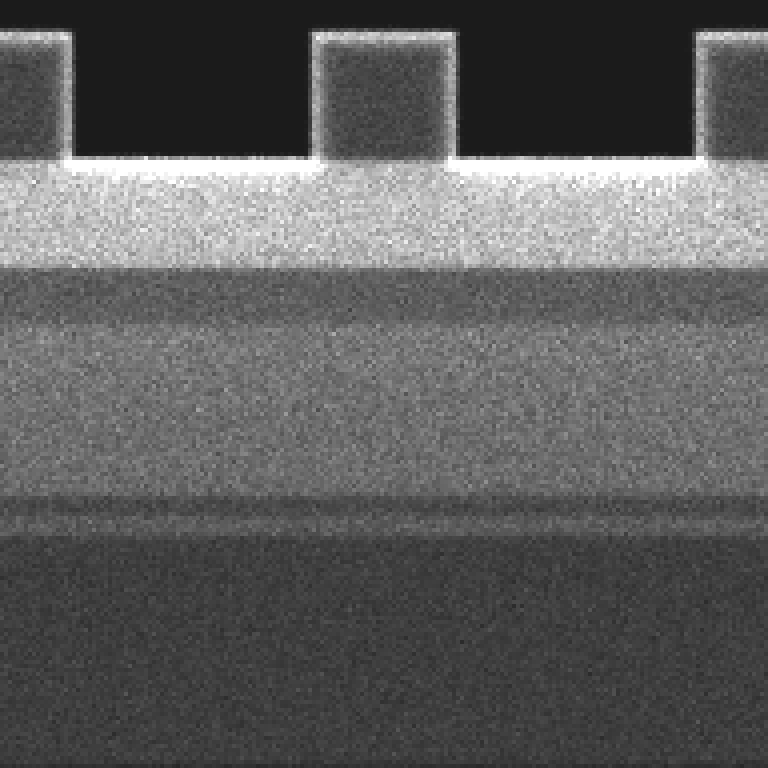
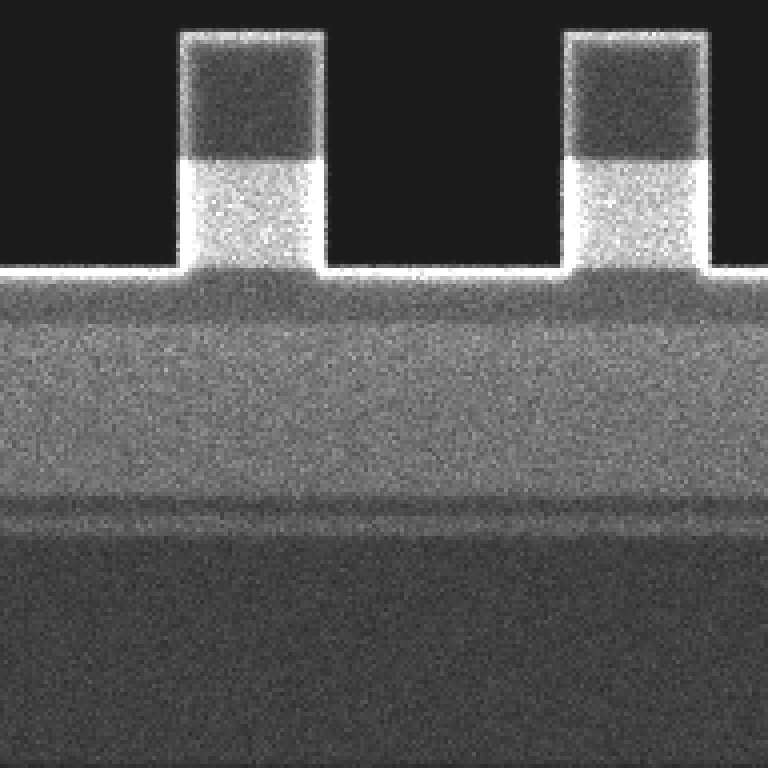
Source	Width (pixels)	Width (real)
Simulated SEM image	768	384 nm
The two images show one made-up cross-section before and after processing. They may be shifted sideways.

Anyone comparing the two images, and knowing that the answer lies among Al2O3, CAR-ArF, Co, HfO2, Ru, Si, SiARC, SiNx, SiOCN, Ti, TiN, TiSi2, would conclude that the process removed HfO2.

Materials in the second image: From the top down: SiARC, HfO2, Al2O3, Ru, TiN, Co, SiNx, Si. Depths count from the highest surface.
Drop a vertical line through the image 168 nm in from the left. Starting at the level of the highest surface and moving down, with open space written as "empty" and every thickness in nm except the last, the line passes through empty 118, Al2O3 28, Ru 86, TiN 10, Co 10, SiNx 114, Si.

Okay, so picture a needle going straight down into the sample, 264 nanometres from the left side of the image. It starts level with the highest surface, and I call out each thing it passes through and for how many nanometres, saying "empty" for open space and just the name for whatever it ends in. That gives empty 118, Al2O3 28, Ru 86, TiN 10, Co 10, SiNx 114, Si